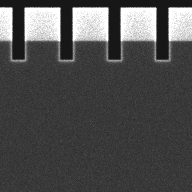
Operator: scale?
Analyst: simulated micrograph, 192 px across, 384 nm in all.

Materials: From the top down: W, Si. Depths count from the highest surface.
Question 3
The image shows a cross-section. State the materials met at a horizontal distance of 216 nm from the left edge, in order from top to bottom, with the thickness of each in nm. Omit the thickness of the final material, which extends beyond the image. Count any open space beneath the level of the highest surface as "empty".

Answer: empty 104, Si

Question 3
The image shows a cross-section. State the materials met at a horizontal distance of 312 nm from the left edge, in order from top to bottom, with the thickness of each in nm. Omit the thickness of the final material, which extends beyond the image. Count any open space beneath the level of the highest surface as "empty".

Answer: empty 104, Si